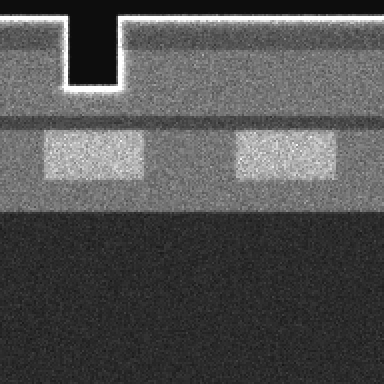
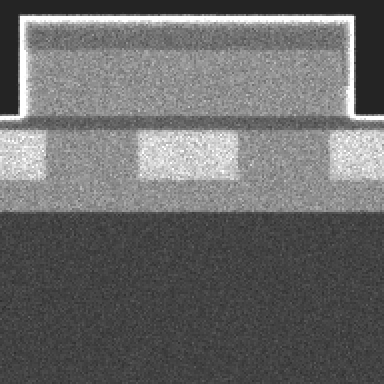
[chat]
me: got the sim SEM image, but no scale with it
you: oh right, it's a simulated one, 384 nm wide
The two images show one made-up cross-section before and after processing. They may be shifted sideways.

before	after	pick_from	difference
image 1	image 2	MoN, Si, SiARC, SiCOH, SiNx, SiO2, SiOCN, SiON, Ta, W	SiO2 removed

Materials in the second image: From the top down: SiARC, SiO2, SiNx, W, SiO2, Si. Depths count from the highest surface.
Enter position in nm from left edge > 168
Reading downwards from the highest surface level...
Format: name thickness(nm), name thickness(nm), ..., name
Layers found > SiARC 34, SiO2 66, SiNx 14, W 50, SiO2 32, Si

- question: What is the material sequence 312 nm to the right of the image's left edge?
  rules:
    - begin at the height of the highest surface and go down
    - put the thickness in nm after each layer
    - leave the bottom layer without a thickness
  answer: SiARC 34, SiO2 66, SiNx 14, SiO2 82, Si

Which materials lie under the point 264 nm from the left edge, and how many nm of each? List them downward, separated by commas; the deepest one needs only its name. SiARC 34, SiO2 66, SiNx 14, SiO2 82, Si